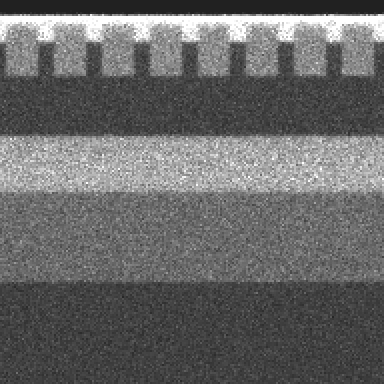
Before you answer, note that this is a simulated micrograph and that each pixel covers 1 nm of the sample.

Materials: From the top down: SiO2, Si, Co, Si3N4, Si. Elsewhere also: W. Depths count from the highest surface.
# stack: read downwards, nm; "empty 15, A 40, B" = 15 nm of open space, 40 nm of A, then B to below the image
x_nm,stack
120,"SiO2 60, Si 60, Co 56, Si3N4 90, Si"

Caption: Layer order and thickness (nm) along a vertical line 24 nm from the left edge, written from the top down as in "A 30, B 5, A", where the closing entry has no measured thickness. SiO2 60, Si 60, Co 56, Si3N4 90, Si